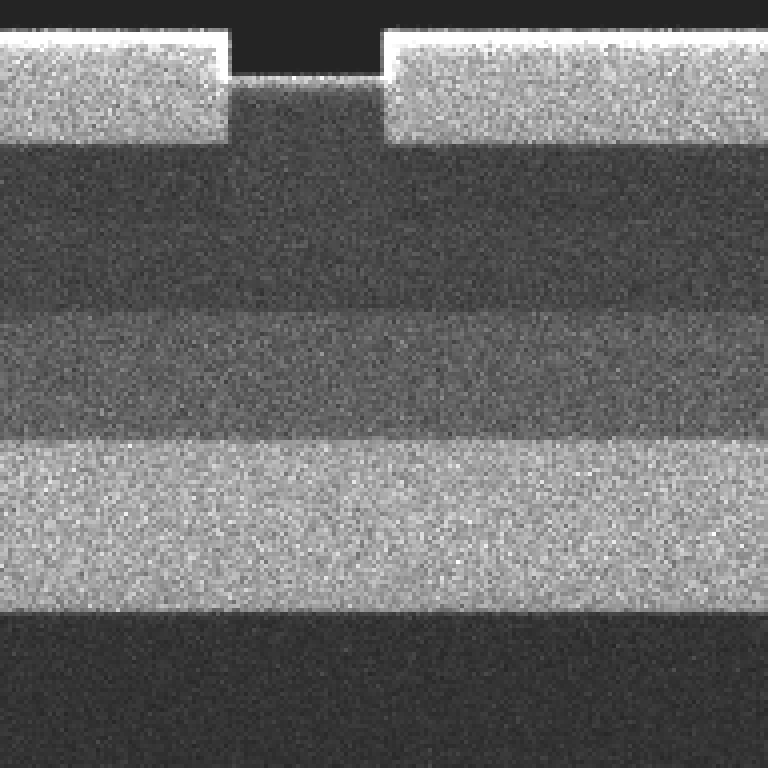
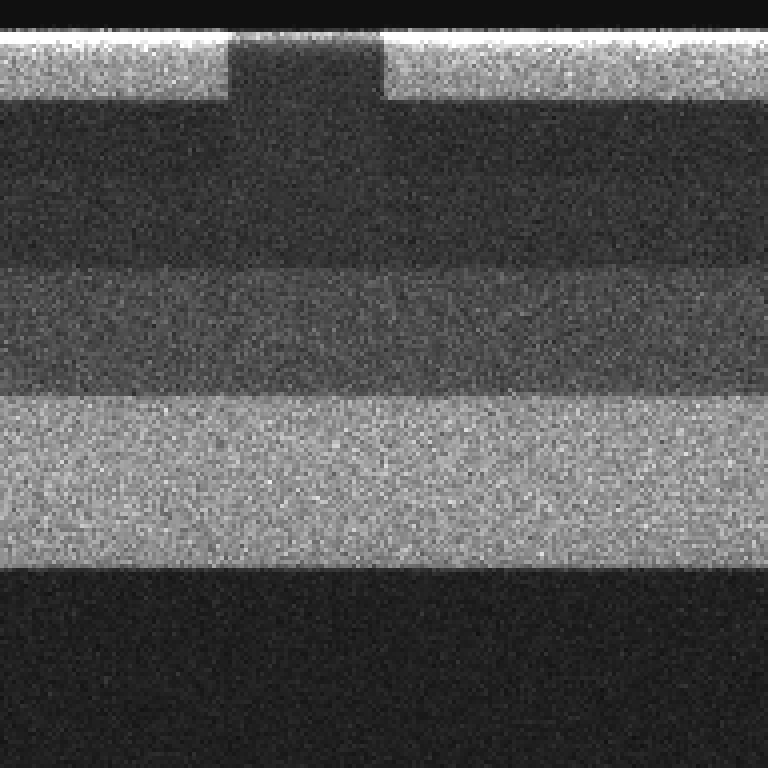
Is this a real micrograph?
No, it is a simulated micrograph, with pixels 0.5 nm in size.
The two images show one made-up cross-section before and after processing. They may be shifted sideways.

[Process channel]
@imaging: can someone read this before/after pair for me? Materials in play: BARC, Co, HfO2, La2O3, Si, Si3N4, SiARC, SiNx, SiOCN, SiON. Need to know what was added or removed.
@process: HfO2 removed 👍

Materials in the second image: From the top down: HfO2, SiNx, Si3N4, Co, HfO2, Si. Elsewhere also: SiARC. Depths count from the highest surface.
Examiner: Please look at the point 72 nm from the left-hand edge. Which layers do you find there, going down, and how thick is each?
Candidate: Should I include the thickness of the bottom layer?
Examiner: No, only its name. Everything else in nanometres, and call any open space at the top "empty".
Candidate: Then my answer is HfO2 34, SiNx 38, Si3N4 46, Co 64, HfO2 86, Si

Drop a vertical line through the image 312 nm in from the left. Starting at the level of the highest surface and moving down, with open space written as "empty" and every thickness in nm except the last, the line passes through HfO2 34, SiNx 38, Si3N4 46, Co 64, HfO2 86, Si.